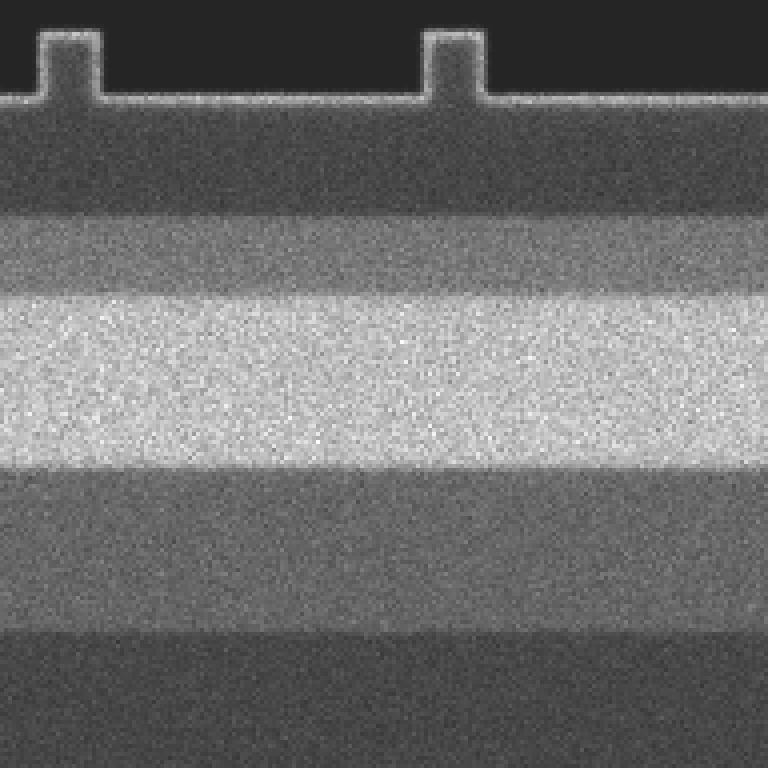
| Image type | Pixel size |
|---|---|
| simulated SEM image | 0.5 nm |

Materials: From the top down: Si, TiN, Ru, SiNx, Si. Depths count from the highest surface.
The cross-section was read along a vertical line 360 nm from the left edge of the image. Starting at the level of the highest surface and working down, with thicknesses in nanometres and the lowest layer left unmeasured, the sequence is empty 32, Si 60, TiN 40, Ru 86, SiNx 82, Si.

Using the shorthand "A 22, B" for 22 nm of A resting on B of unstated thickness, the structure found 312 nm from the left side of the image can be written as empty 32, Si 60, TiN 40, Ru 86, SiNx 82, Si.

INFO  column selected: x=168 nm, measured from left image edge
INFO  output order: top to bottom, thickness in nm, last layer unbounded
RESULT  empty 32, Si 60, TiN 40, Ru 86, SiNx 82, Si